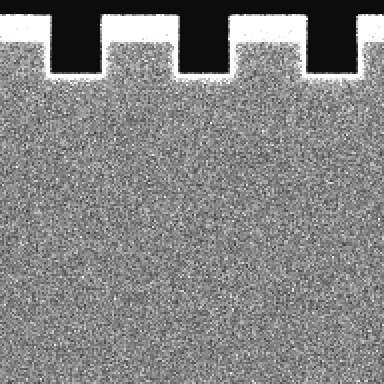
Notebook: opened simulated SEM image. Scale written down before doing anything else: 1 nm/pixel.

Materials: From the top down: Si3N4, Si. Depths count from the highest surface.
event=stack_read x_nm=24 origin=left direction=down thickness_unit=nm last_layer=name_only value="Si3N4 26, Si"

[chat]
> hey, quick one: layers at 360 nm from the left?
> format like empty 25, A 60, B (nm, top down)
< Si3N4 26, Si